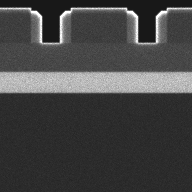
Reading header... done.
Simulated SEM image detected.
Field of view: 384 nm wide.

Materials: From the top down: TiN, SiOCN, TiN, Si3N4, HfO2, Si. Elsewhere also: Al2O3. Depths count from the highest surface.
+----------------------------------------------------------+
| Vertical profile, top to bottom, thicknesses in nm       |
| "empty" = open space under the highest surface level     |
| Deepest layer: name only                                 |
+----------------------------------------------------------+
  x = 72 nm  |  empty 6, Al2O3 64, TiN 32, Si3N4 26, HfO2 42, Si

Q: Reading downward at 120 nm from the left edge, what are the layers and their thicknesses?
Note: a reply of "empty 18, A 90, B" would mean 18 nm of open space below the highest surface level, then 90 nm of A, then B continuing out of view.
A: empty 16, Al2O3 54, TiN 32, Si3N4 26, HfO2 42, Si